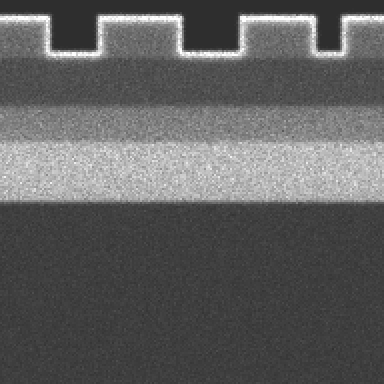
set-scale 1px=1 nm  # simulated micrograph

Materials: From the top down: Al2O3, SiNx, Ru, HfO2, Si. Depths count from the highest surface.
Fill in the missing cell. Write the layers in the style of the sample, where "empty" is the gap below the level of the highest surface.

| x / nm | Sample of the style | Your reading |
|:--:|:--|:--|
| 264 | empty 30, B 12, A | Al2O3 42, SiNx 48, Ru 36, HfO2 60, Si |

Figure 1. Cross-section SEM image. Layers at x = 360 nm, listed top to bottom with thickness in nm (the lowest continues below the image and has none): Al2O3 42, SiNx 48, Ru 36, HfO2 60, Si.